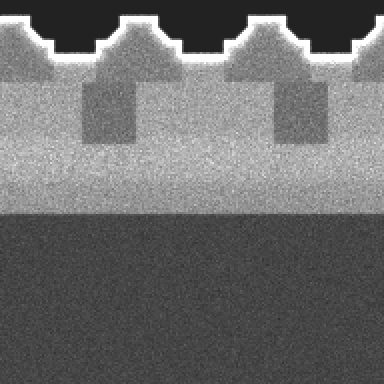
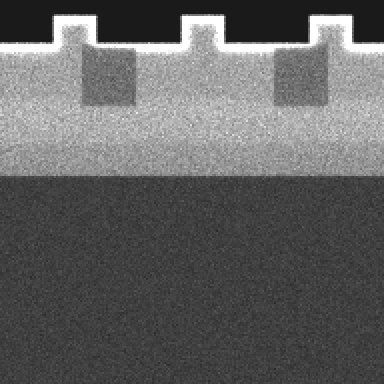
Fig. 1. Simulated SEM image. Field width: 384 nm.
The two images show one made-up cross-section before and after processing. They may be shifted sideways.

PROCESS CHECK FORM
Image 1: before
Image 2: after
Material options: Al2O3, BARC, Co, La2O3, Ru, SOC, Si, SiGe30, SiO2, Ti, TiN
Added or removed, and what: removed, SOC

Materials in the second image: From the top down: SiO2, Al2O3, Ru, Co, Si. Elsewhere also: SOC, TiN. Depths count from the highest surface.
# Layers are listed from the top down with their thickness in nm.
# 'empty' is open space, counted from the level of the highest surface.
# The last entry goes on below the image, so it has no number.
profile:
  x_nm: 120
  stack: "empty 28, TiN 62, Ru 38, Co 32, Si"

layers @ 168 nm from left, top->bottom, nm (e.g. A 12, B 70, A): empty 28, Al2O3 54, Ru 46, Co 32, Si